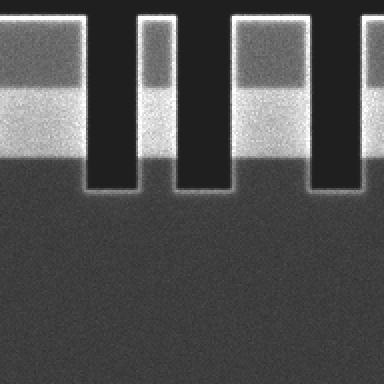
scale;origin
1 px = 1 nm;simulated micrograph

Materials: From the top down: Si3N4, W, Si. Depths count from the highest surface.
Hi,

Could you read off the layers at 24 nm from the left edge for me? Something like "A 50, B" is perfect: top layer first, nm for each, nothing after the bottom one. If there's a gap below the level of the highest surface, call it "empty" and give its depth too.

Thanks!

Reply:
Si3N4 72, W 70, Si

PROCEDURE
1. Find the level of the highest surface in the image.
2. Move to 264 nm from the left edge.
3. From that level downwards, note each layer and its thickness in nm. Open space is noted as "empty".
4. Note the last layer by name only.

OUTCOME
Si3N4 72, W 70, Si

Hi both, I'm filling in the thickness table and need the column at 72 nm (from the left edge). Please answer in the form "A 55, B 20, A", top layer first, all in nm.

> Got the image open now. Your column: Si3N4 72, W 70, Si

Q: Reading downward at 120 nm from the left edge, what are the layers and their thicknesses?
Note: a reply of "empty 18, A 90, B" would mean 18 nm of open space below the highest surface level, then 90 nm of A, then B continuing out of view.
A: empty 174, Si